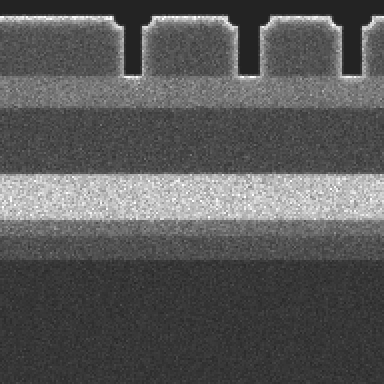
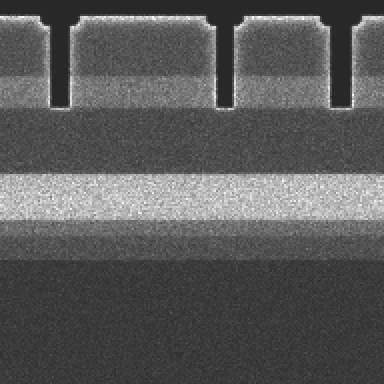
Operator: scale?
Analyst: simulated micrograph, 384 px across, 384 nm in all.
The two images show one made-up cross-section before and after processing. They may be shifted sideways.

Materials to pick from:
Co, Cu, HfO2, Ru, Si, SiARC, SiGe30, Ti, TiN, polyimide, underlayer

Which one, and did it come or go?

Ru - removed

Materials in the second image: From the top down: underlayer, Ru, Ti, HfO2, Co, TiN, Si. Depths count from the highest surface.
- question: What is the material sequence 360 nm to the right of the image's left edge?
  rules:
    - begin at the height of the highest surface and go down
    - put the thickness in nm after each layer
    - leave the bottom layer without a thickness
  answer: empty 6, underlayer 54, Ru 32, Ti 66, HfO2 46, Co 16, TiN 24, Si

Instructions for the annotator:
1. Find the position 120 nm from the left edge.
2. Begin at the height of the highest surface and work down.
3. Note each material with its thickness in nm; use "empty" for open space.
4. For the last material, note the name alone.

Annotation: underlayer 60, Ru 32, Ti 66, HfO2 46, Co 16, TiN 24, Si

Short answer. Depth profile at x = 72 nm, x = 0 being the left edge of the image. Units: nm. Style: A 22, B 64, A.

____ empty 10, underlayer 50, Ru 32, Ti 66, HfO2 46, Co 16, TiN 24, Si